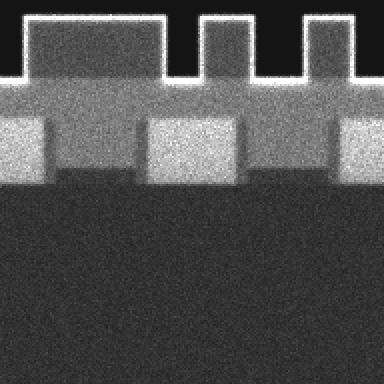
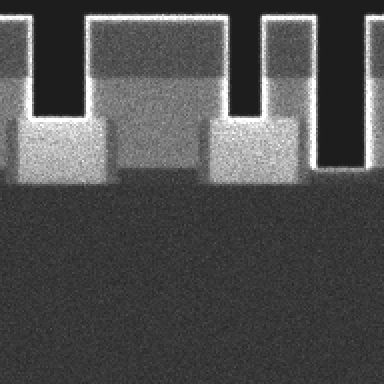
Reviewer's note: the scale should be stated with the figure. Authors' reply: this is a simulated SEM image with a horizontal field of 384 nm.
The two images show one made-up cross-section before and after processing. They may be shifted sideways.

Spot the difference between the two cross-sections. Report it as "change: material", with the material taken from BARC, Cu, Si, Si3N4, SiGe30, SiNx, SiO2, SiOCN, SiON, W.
removed: SiO2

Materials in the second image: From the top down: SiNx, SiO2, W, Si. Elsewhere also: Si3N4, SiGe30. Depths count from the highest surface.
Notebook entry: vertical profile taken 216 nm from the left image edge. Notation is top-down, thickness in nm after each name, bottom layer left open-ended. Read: SiNx 62, SiO2 40, W 66, Si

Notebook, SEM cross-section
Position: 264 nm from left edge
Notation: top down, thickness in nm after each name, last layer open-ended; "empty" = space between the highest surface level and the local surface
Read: SiNx 62, SiO2 40, W 66, Si